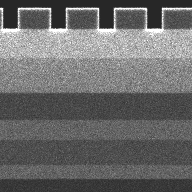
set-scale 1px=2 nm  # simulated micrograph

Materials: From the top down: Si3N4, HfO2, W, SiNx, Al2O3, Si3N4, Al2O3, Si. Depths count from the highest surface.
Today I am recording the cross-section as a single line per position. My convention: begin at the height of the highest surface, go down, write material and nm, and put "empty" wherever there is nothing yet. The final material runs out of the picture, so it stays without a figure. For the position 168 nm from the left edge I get Si3N4 42, HfO2 58, W 70, SiNx 54, Al2O3 40, Si3N4 50, Al2O3 28, Si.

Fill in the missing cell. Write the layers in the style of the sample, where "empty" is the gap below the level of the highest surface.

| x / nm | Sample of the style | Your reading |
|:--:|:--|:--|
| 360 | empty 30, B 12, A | Si3N4 42, HfO2 58, W 70, SiNx 54, Al2O3 40, Si3N4 50, Al2O3 28, Si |